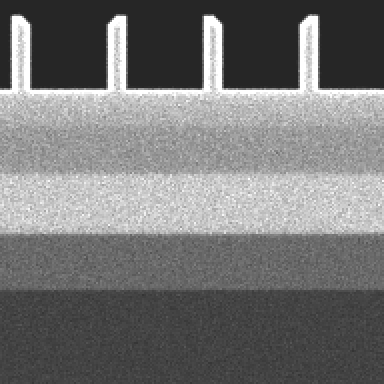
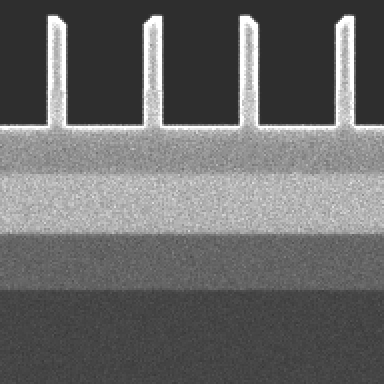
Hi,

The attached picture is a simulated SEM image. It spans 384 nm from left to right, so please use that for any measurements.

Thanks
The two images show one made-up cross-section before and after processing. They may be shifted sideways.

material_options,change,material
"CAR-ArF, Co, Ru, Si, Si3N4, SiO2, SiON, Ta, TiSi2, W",removed,Ru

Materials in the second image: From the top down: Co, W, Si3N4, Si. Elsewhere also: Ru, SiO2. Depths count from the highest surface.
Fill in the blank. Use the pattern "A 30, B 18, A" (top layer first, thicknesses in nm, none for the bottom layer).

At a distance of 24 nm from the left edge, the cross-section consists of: empty 110, Co 48, W 60, Si3N4 56, Si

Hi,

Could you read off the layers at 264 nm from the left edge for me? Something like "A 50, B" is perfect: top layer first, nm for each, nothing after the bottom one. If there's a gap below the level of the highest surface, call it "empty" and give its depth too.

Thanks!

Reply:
empty 110, Co 48, W 60, Si3N4 56, Si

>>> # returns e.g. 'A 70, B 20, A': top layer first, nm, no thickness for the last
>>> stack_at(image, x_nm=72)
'empty 110, Co 48, W 60, Si3N4 56, Si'